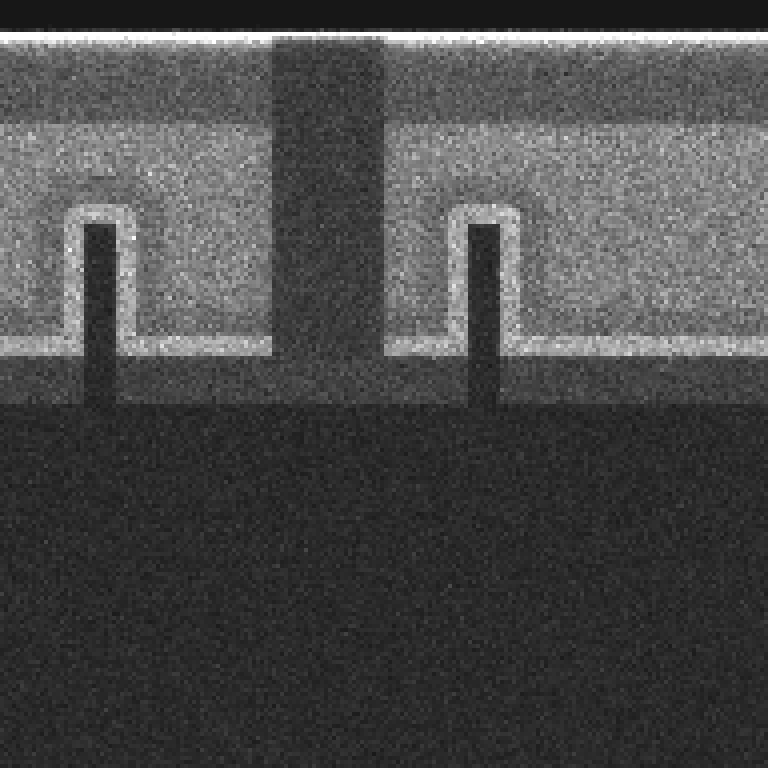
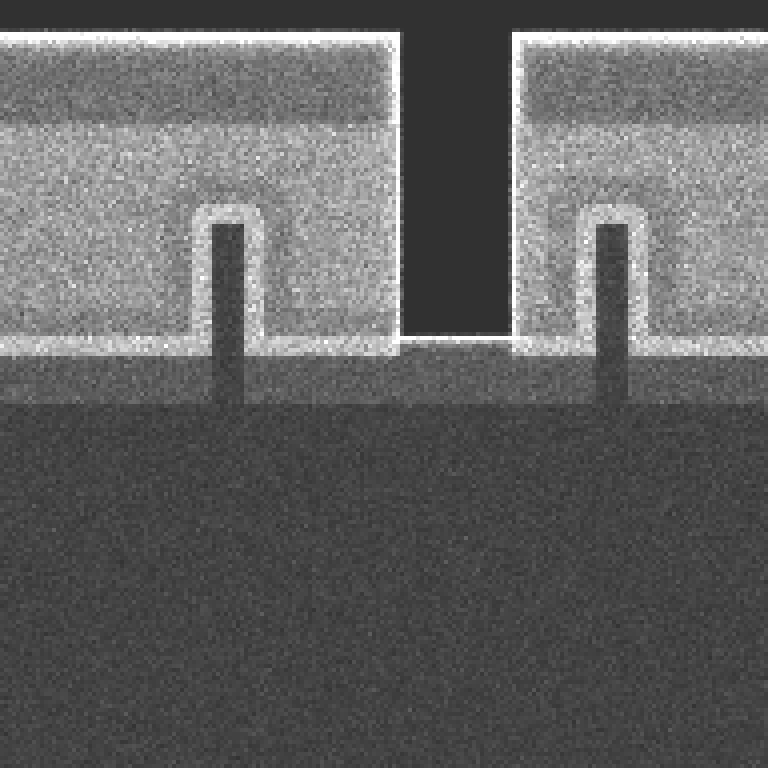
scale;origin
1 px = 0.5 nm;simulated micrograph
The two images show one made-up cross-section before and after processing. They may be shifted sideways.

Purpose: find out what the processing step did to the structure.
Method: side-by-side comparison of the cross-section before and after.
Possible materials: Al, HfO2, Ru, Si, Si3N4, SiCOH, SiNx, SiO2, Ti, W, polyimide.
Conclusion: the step removed SiNx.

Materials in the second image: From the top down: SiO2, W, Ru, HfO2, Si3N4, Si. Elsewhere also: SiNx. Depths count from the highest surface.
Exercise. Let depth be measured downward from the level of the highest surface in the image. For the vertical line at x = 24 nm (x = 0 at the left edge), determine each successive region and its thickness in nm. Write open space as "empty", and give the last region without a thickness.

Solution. SiO2 46, W 92, Ru 14, HfO2 10, Si3N4 24, Si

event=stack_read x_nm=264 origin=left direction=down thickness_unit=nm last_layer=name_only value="SiO2 46, W 92, Ru 14, HfO2 10, Si3N4 24, Si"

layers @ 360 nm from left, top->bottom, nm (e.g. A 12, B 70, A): SiO2 46, W 92, Ru 14, HfO2 10, Si3N4 24, Si